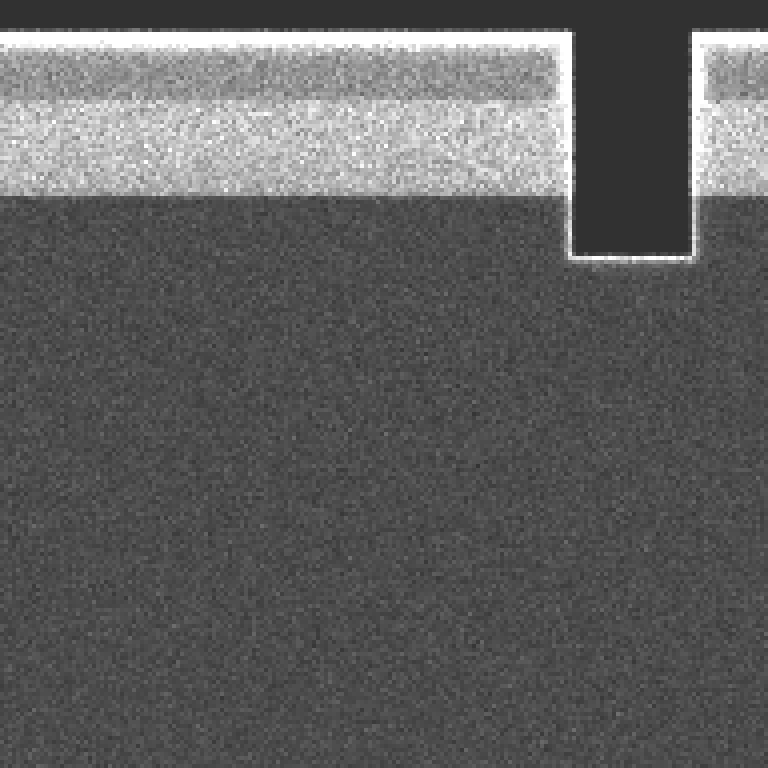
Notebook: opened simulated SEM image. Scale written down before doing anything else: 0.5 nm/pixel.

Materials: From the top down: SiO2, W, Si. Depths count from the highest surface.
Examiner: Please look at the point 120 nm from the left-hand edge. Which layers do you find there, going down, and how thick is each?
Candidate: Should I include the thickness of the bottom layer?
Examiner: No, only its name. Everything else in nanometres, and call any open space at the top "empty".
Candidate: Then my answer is SiO2 34, W 48, Si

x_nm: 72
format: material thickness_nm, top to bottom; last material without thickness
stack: SiO2 34, W 48, Si